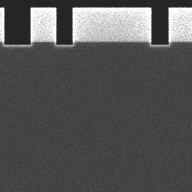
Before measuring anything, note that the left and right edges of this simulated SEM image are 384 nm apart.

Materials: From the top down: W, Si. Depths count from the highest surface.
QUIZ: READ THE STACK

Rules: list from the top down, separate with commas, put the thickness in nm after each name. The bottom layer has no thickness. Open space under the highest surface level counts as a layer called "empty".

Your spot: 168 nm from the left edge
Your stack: W 68, Si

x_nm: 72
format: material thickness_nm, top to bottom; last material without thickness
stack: W 68, Si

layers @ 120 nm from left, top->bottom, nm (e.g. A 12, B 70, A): empty 74, Si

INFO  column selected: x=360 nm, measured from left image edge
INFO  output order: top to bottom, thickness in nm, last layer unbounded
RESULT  W 68, Si